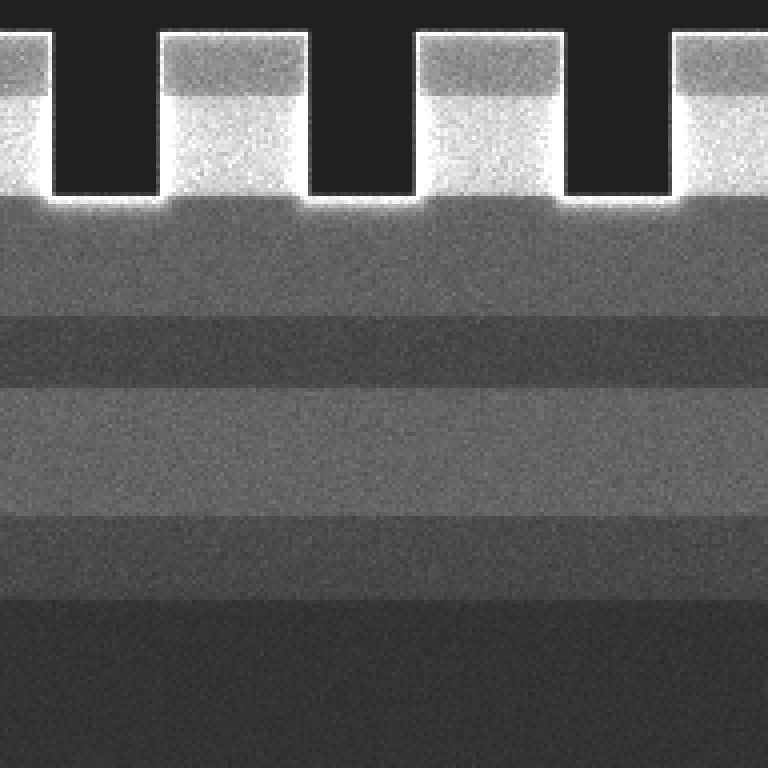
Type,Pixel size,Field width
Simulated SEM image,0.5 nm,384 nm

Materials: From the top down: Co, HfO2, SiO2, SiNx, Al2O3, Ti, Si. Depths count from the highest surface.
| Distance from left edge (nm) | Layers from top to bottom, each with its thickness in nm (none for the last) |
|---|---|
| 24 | Co 32, HfO2 50, SiO2 60, SiNx 36, Al2O3 64, Ti 42, Si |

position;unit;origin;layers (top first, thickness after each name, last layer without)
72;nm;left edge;empty 82, SiO2 60, SiNx 36, Al2O3 64, Ti 42, Si